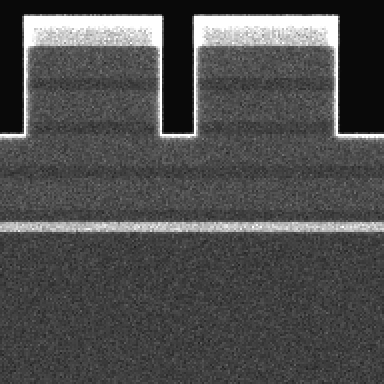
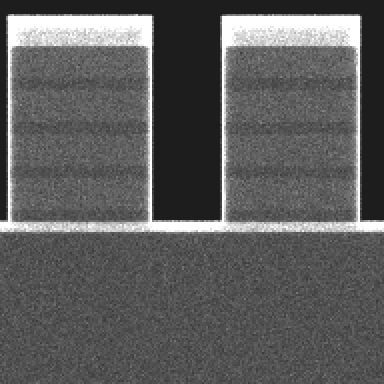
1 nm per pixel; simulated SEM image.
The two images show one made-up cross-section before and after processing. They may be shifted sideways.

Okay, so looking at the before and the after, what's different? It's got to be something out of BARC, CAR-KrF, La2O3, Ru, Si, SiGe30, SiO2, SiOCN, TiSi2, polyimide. Si and SiGe30, removed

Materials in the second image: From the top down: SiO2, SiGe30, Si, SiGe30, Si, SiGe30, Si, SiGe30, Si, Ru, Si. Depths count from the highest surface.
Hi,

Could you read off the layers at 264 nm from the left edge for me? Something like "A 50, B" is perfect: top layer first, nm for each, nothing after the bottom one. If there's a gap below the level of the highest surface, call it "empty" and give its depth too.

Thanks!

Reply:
SiO2 30, SiGe30 32, Si 12, SiGe30 32, Si 12, SiGe30 32, Si 12, SiGe30 32, Si 12, Ru 10, Si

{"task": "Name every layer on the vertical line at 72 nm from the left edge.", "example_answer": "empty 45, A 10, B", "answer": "SiO2 30, SiGe30 32, Si 12, SiGe30 32, Si 12, SiGe30 32, Si 12, SiGe30 32, Si 12, Ru 10, Si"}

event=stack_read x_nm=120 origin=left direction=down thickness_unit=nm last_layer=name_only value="SiO2 30, SiGe30 32, Si 12, SiGe30 32, Si 12, SiGe30 32, Si 12, SiGe30 32, Si 12, Ru 10, Si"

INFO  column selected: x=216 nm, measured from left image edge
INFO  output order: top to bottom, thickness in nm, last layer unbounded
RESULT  empty 206, Ru 10, Si